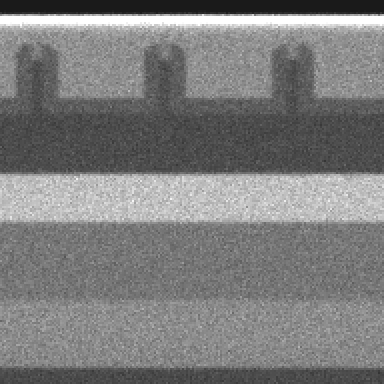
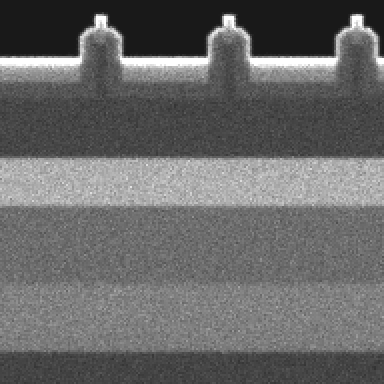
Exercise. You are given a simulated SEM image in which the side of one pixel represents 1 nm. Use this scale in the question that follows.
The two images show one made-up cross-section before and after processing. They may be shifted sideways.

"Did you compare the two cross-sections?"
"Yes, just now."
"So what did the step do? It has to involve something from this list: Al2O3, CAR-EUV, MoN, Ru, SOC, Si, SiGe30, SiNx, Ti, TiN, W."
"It removed SOC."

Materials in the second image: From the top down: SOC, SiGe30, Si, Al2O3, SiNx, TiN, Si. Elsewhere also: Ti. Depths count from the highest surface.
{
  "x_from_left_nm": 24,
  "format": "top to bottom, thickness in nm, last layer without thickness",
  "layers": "empty 42, SOC 24, SiGe30 16, Si 60, Al2O3 48, SiNx 78, TiN 68, Si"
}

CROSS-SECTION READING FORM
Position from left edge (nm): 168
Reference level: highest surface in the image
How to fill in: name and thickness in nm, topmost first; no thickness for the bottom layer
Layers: empty 42, SOC 24, SiGe30 16, Si 60, Al2O3 48, SiNx 78, TiN 68, Si